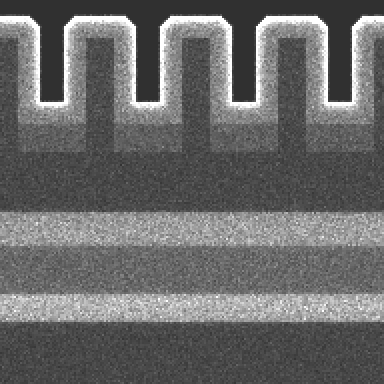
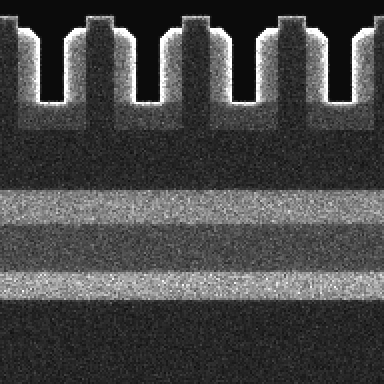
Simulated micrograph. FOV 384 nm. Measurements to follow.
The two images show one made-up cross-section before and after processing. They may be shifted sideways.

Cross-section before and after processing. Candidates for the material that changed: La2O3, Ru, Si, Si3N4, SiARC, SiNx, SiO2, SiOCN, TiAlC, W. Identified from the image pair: SiO2 (removed).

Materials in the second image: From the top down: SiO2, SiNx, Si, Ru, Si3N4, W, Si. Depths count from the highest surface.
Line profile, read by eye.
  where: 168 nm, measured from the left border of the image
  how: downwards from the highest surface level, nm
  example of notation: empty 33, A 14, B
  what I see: empty 14, SiO2 72, SiNx 28, Si 60, Ru 34, Si3N4 48, W 28, Si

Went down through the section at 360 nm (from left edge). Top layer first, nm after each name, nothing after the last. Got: empty 14, SiO2 72, SiNx 28, Si 60, Ru 34, Si3N4 48, W 28, Si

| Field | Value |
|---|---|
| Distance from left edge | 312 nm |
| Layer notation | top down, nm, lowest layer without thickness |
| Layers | empty 12, SiO2 74, SiNx 28, Si 60, Ru 34, Si3N4 48, W 28, Si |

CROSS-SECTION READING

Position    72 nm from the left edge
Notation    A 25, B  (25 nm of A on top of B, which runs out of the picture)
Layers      empty 14, SiO2 72, SiNx 28, Si 60, Ru 34, Si3N4 48, W 28, Si